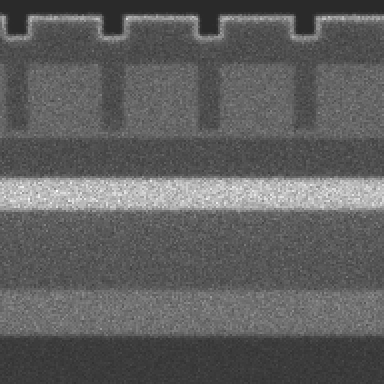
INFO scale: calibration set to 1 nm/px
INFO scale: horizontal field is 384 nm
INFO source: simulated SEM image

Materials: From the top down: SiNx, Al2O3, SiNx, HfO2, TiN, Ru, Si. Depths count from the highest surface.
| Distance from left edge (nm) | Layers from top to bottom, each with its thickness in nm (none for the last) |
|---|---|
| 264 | SiNx 48, Al2O3 74, SiNx 40, HfO2 32, TiN 80, Ru 46, Si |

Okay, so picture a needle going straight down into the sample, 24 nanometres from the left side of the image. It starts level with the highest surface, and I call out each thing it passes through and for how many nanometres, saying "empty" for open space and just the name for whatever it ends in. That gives empty 20, SiNx 94, Al2O3 8, SiNx 40, HfO2 32, TiN 80, Ru 46, Si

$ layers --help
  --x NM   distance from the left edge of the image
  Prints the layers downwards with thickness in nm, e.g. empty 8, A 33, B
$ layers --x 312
empty 20, SiNx 94, Al2O3 8, SiNx 40, HfO2 32, TiN 80, Ru 46, Si